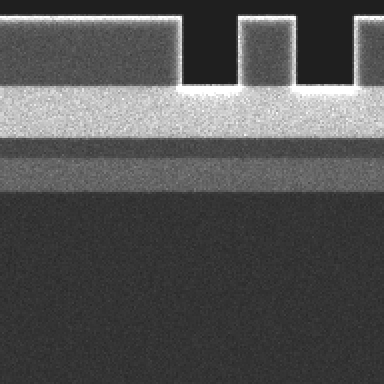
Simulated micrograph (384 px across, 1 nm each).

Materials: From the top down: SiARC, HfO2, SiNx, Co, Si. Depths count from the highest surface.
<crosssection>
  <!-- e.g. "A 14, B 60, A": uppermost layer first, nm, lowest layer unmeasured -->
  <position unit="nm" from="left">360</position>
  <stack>SiARC 70, HfO2 52, SiNx 20, Co 34, Si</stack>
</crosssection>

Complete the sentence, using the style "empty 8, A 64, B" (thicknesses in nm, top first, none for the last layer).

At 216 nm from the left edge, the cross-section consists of empty 70, HfO2 52, SiNx 20, Co 34, Si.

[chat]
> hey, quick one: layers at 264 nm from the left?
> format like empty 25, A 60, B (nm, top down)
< SiARC 70, HfO2 52, SiNx 20, Co 34, Si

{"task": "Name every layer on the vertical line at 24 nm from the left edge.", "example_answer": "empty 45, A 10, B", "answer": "SiARC 70, HfO2 52, SiNx 20, Co 34, Si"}